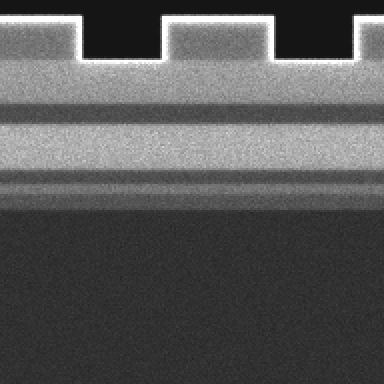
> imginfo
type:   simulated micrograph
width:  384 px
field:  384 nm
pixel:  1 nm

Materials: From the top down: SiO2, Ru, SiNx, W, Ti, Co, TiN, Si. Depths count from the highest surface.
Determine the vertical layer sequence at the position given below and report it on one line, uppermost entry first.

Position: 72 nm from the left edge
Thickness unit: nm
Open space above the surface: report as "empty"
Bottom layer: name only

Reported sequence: SiO2 44, Ru 44, SiNx 20, W 46, Ti 14, Co 10, TiN 16, Si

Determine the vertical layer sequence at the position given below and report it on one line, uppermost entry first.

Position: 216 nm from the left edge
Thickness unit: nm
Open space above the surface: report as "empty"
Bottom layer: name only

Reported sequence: SiO2 44, Ru 44, SiNx 20, W 46, Ti 14, Co 10, TiN 16, Si